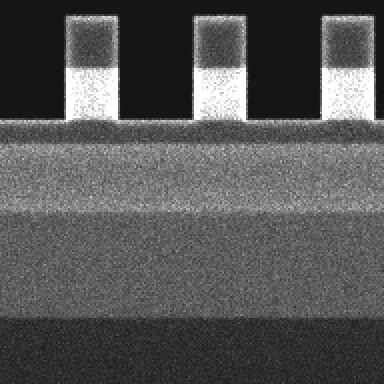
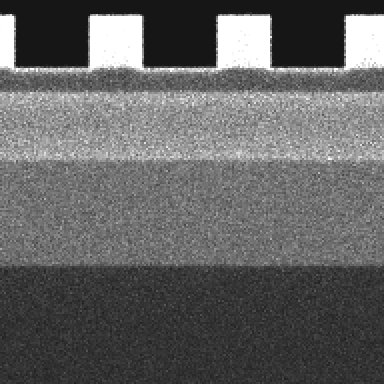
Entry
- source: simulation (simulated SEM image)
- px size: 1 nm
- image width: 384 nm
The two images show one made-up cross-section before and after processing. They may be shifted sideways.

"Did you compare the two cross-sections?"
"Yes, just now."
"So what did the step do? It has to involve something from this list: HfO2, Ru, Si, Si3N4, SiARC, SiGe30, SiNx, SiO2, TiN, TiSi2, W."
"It removed SiARC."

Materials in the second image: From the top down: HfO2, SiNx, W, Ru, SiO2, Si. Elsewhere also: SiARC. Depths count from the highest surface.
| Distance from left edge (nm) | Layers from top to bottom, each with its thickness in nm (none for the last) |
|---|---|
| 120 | HfO2 52, SiNx 24, W 52, Ru 16, SiO2 106, Si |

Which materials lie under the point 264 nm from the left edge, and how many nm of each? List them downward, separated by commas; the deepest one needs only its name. HfO2 52, SiNx 24, W 52, Ru 16, SiO2 106, Si